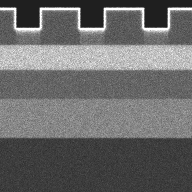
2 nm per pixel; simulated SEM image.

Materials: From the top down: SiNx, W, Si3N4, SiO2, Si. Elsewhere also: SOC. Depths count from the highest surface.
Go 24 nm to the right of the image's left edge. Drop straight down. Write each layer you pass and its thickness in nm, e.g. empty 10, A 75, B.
SiNx 74, W 50, Si3N4 58, SiO2 78, Si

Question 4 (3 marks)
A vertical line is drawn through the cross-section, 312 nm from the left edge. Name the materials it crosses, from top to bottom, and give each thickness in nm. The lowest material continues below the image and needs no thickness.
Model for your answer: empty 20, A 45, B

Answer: empty 40, SOC 34, W 50, Si3N4 58, SiO2 78, Si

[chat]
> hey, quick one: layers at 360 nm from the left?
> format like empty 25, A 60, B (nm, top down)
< SiNx 74, W 50, Si3N4 58, SiO2 78, Si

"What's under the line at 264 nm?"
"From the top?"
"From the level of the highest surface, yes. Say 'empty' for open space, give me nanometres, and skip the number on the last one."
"SiNx 74, W 50, Si3N4 58, SiO2 78, Si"